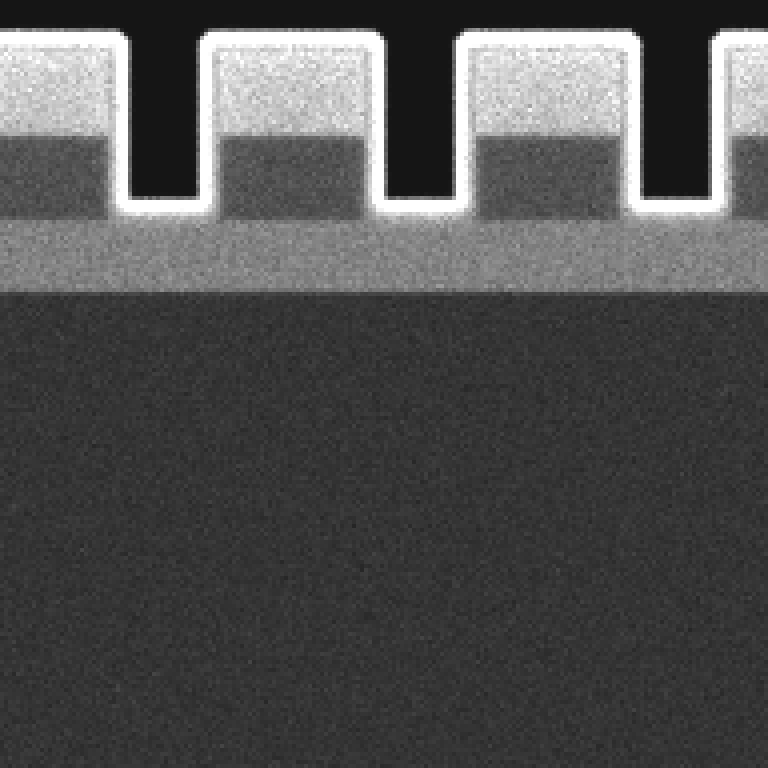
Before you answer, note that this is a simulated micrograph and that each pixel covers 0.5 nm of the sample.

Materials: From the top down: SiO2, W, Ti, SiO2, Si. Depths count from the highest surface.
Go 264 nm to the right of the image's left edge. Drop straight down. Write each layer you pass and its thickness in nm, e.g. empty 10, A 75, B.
SiO2 10, W 42, Ti 42, SiO2 36, Si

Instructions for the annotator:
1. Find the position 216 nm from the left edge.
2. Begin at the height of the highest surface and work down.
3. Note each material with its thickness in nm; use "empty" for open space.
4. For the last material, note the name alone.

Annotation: empty 84, SiO2 46, Si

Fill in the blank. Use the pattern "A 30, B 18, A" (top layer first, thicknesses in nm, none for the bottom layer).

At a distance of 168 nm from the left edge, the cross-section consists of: SiO2 10, W 42, Ti 42, SiO2 36, Si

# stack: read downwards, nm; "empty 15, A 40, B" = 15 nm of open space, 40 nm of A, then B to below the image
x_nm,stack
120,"SiO2 10, W 42, Ti 42, SiO2 36, Si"